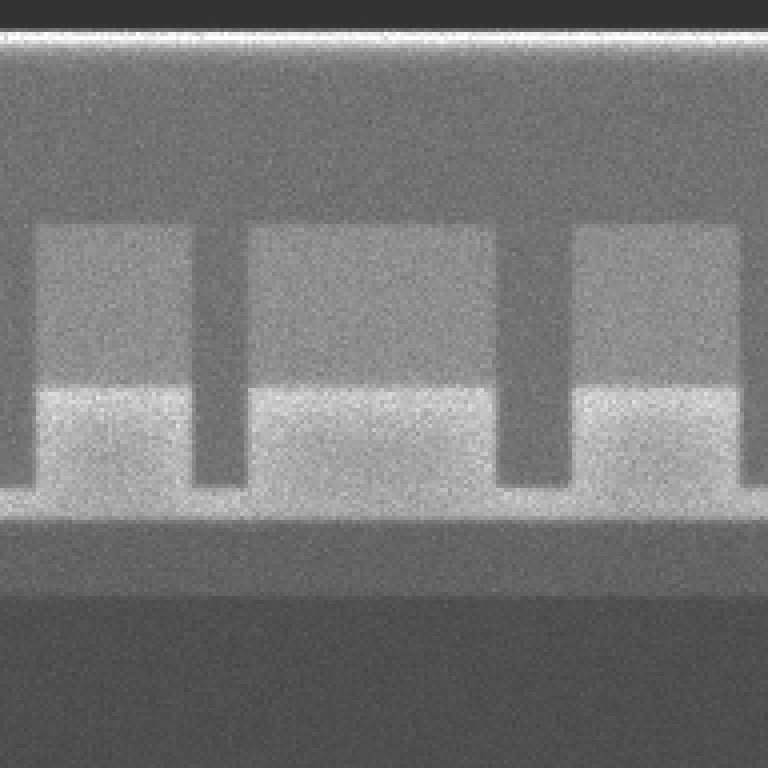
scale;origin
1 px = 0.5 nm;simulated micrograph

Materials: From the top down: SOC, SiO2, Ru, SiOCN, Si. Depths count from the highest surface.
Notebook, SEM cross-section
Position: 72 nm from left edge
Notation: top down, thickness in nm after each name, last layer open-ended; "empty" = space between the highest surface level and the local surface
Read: SOC 96, SiO2 82, Ru 66, SiOCN 38, Si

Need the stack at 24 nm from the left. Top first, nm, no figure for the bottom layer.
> SOC 96, SiO2 82, Ru 66, SiOCN 38, Si